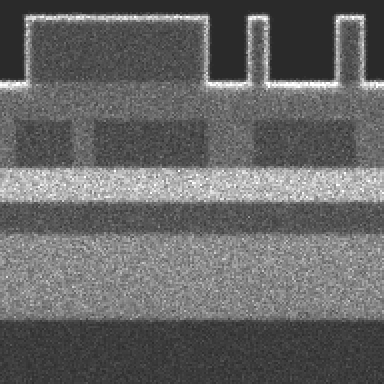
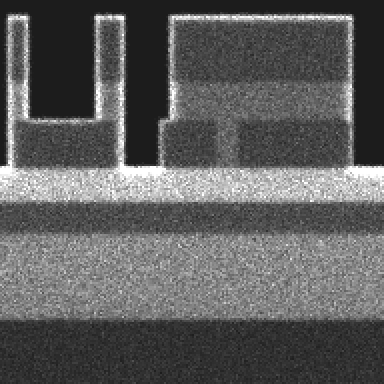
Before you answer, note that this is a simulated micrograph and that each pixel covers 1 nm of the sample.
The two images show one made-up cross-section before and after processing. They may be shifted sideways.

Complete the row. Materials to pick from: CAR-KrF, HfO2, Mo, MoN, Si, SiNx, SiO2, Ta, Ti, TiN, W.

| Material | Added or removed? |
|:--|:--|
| SiO2 | removed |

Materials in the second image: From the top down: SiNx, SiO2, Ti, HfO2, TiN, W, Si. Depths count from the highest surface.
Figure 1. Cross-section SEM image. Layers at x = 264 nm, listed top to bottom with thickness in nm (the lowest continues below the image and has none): SiNx 66, SiO2 38, Ti 48, HfO2 34, TiN 32, W 86, Si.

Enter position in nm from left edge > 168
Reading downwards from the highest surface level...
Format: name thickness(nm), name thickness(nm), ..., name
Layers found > empty 104, Ti 48, HfO2 34, TiN 32, W 86, Si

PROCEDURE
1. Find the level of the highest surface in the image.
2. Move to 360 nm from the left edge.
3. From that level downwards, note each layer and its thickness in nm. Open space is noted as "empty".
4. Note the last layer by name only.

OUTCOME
empty 152, HfO2 34, TiN 32, W 86, Si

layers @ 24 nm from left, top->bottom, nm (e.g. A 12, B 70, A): SiNx 66, SiO2 38, Ti 48, HfO2 34, TiN 32, W 86, Si